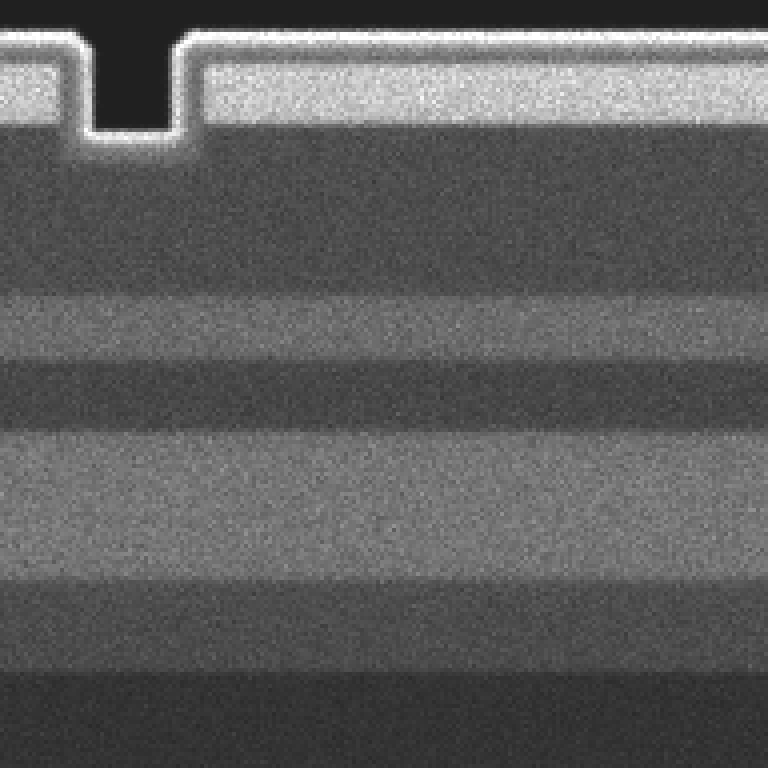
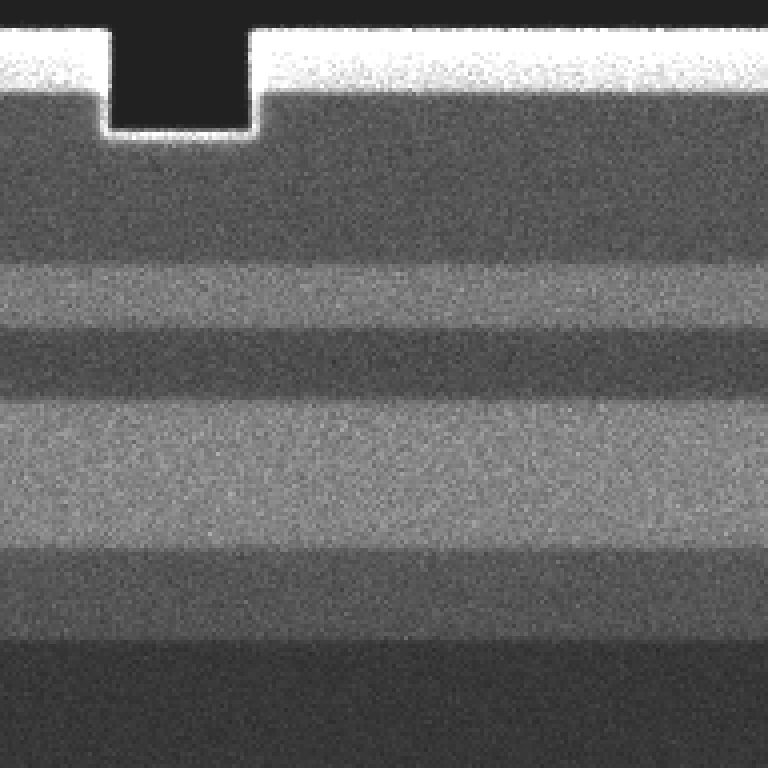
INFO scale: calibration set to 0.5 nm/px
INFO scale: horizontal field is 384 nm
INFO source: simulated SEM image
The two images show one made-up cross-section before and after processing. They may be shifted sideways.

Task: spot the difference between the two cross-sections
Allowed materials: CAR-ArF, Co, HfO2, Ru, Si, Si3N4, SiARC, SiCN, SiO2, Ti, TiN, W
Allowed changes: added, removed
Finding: removed SiO2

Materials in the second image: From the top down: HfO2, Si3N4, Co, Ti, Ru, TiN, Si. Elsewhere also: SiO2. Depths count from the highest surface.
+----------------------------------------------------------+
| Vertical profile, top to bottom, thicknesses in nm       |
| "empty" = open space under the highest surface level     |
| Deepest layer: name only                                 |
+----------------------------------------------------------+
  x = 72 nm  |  empty 50, Si3N4 66, Co 32, Ti 36, Ru 74, TiN 46, Si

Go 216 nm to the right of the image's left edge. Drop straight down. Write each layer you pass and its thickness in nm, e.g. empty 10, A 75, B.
HfO2 30, Si3N4 86, Co 32, Ti 36, Ru 74, TiN 46, Si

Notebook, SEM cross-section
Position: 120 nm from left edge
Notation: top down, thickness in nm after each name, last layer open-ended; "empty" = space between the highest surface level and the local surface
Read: empty 50, Si3N4 66, Co 32, Ti 36, Ru 74, TiN 46, Si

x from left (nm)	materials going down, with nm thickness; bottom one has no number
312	HfO2 30, Si3N4 86, Co 32, Ti 36, Ru 74, TiN 46, Si